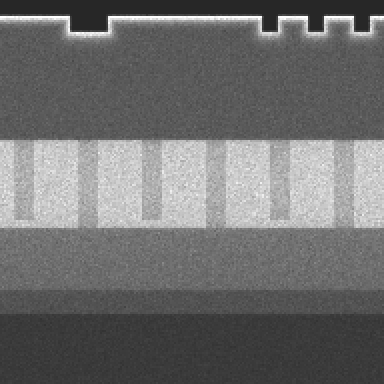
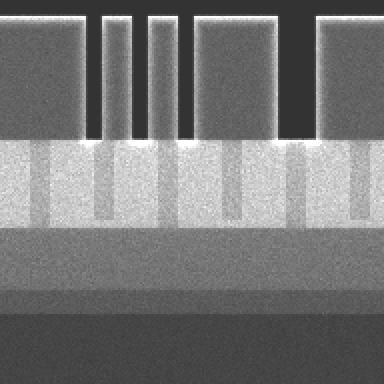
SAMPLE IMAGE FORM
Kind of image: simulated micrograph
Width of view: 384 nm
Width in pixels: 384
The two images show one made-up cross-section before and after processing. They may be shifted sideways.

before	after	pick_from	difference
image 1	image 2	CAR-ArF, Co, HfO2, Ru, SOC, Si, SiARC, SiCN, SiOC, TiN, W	SOC removed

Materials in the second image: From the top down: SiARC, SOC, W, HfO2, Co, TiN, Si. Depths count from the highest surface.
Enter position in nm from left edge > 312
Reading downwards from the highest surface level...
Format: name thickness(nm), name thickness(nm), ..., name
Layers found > empty 124, HfO2 88, Co 62, TiN 24, Si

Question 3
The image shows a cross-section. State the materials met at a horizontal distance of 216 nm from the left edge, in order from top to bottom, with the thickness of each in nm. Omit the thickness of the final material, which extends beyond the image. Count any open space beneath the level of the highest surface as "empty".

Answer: SiARC 16, SOC 108, HfO2 88, Co 62, TiN 24, Si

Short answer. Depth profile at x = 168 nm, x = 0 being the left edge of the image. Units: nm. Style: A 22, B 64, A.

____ SiARC 16, SOC 108, W 88, Co 62, TiN 24, Si